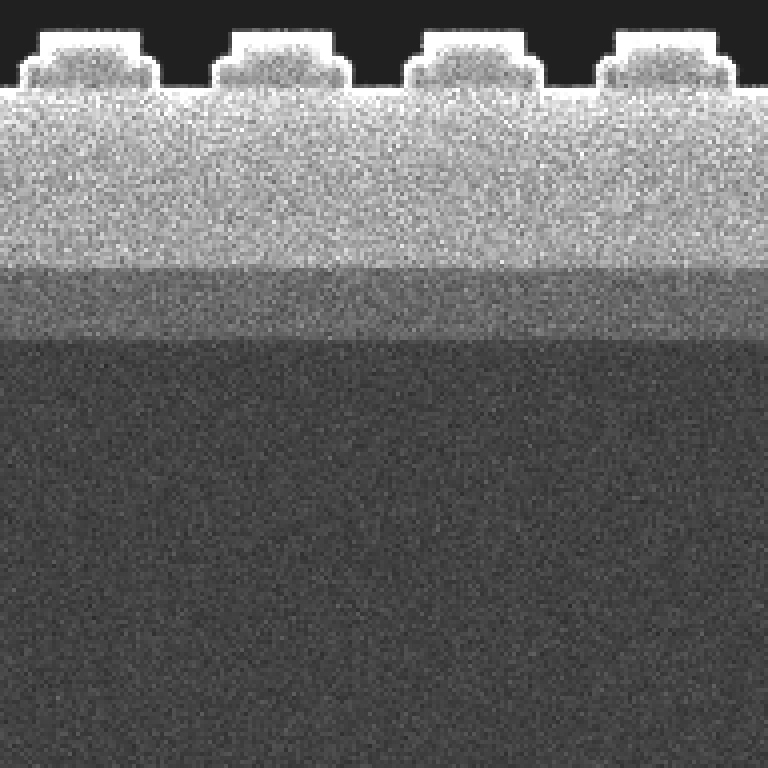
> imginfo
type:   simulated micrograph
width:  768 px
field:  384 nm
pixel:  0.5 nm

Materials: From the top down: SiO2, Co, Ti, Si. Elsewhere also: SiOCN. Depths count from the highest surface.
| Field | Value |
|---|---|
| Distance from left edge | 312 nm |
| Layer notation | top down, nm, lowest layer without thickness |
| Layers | SiO2 28, Co 90, Ti 36, Si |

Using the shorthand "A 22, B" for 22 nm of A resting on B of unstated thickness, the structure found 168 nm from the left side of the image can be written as empty 12, SiOCN 16, Co 90, Ti 36, Si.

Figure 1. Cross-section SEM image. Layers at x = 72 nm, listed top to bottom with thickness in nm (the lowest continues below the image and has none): empty 12, SiOCN 16, Co 90, Ti 36, Si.